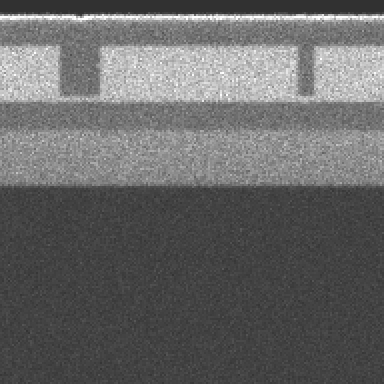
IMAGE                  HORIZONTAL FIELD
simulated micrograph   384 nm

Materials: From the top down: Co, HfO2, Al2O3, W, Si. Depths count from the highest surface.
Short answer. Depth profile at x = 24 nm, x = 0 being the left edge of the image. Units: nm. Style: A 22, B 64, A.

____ Co 30, HfO2 56, Al2O3 28, W 56, Si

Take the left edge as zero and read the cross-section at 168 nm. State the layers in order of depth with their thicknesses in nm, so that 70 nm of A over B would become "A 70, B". Co 30, HfO2 56, Al2O3 28, W 56, Si